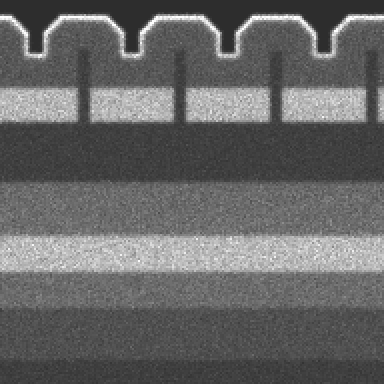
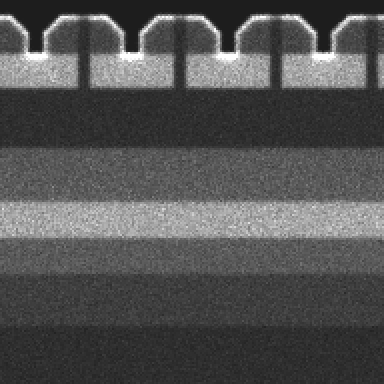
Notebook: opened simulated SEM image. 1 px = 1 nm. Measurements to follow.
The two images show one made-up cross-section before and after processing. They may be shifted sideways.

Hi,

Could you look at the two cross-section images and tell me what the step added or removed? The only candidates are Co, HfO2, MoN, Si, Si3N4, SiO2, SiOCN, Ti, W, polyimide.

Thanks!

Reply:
removed Si3N4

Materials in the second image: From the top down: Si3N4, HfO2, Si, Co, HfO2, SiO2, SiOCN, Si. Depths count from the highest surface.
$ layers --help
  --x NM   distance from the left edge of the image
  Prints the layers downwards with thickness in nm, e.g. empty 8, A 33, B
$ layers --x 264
Si3N4 38, HfO2 34, Si 60, Co 54, HfO2 36, SiO2 36, SiOCN 52, Si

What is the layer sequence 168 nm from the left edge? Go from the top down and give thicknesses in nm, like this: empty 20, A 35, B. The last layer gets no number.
Si3N4 38, HfO2 34, Si 60, Co 54, HfO2 36, SiO2 36, SiOCN 52, Si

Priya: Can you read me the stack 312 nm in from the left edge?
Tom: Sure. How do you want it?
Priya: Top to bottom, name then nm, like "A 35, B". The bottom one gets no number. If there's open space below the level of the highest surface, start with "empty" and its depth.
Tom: empty 14, Si3N4 24, HfO2 34, Si 60, Co 54, HfO2 36, SiO2 36, SiOCN 52, Si